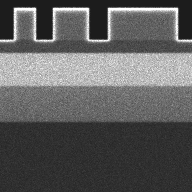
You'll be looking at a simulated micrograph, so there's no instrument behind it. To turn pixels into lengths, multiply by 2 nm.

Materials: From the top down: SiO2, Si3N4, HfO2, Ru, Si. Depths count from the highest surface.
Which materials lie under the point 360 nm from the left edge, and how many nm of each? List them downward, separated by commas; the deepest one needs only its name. empty 64, Si3N4 26, HfO2 66, Ru 72, Si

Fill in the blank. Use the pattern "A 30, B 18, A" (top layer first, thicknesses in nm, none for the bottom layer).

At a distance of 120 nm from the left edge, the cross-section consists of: SiO2 64, Si3N4 26, HfO2 66, Ru 72, Si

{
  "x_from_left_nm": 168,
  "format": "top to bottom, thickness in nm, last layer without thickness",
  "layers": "SiO2 64, Si3N4 26, HfO2 66, Ru 72, Si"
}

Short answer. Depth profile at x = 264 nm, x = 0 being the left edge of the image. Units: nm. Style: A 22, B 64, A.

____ SiO2 64, Si3N4 26, HfO2 66, Ru 72, Si